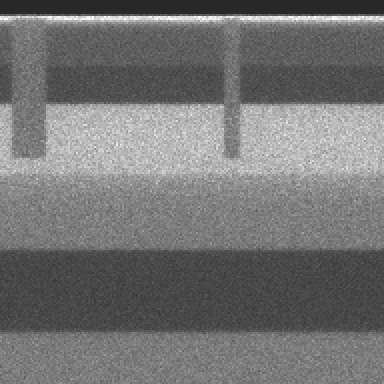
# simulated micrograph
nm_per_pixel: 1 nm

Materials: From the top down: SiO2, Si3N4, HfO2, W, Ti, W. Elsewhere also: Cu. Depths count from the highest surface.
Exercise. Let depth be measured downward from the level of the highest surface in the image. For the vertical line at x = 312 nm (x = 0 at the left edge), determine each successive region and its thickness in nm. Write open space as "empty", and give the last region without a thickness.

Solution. SiO2 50, Si3N4 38, HfO2 70, W 76, Ti 82, W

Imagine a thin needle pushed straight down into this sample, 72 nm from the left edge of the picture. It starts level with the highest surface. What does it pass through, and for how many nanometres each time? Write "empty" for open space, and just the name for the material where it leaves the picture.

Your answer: SiO2 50, Si3N4 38, HfO2 70, W 76, Ti 82, W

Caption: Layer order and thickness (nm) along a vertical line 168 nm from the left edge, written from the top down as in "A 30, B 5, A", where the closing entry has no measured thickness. SiO2 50, Si3N4 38, HfO2 70, W 76, Ti 82, W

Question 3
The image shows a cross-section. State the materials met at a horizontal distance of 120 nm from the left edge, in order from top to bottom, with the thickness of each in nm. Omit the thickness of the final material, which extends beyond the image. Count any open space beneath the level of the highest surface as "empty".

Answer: SiO2 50, Si3N4 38, HfO2 70, W 76, Ti 82, W